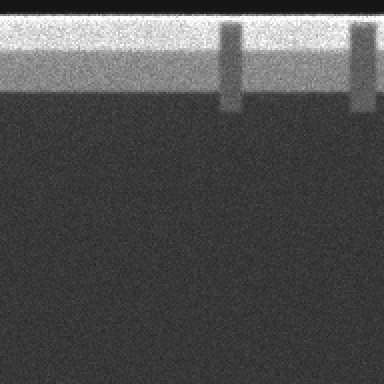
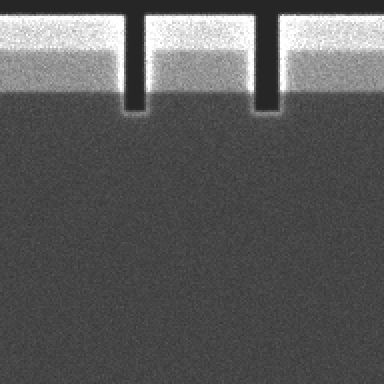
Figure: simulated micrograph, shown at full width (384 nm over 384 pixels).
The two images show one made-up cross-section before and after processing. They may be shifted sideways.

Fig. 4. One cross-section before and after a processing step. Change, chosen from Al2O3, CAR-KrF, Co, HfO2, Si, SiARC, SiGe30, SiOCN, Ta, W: SiARC removed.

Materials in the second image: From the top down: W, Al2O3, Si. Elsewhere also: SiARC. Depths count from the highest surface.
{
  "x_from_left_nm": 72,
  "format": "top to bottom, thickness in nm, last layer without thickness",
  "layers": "W 34, Al2O3 42, Si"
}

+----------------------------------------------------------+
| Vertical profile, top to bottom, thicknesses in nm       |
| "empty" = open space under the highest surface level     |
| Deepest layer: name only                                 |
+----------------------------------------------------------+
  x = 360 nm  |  W 34, Al2O3 42, Si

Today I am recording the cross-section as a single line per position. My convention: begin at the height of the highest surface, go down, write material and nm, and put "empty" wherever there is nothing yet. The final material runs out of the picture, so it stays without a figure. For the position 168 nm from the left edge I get W 34, Al2O3 42, Si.